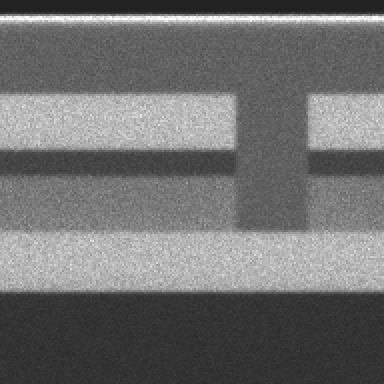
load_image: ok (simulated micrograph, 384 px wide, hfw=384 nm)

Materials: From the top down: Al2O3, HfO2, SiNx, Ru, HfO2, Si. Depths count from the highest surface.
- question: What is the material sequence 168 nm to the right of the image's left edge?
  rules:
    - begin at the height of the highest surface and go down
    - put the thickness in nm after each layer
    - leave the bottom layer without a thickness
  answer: Al2O3 78, HfO2 56, SiNx 26, Ru 56, HfO2 60, Si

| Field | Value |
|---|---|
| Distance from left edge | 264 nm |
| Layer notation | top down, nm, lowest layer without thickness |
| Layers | Al2O3 216, HfO2 60, Si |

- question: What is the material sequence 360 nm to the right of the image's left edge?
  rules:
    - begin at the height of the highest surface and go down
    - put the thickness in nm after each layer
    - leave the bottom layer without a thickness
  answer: Al2O3 78, HfO2 56, SiNx 26, Ru 56, HfO2 60, Si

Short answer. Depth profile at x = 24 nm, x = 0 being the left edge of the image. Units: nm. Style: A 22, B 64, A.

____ Al2O3 78, HfO2 56, SiNx 26, Ru 56, HfO2 60, Si